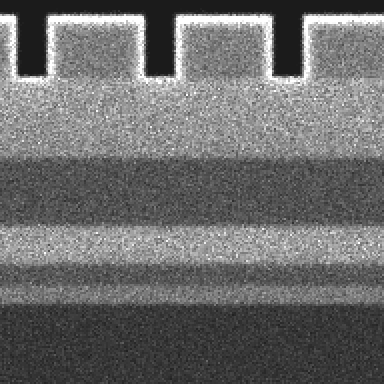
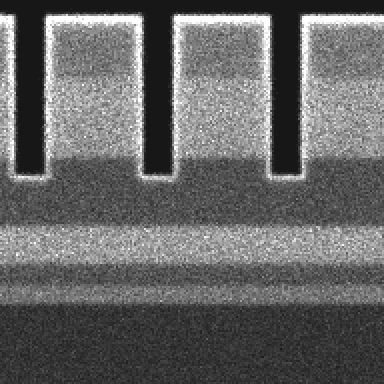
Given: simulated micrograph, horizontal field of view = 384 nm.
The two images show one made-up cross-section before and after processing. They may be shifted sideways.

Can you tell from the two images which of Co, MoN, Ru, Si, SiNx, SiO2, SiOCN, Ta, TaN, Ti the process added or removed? Yes, it removed Co and SiNx.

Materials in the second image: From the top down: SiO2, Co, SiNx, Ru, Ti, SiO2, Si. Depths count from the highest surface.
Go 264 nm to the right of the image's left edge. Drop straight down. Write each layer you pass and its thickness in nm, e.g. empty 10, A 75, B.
SiO2 62, Co 80, SiNx 68, Ru 38, Ti 22, SiO2 18, Si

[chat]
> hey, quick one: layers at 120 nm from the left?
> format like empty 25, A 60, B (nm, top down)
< SiO2 62, Co 80, SiNx 68, Ru 38, Ti 22, SiO2 18, Si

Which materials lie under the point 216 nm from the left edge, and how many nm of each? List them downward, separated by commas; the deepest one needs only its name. SiO2 62, Co 80, SiNx 68, Ru 38, Ti 22, SiO2 18, Si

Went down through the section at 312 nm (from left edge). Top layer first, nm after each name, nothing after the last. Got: SiO2 62, Co 80, SiNx 68, Ru 38, Ti 22, SiO2 18, Si